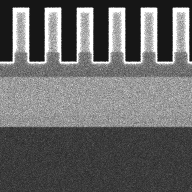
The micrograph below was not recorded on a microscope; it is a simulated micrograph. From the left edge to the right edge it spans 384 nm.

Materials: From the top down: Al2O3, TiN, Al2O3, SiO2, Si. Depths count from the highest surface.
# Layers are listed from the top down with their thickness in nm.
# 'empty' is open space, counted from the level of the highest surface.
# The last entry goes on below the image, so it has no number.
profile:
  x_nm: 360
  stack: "Al2O3 88, TiN 50, Al2O3 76, SiO2 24, Si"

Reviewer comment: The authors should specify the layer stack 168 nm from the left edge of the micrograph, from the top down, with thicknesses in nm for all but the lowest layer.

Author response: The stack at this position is Al2O3 88, TiN 50, Al2O3 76, SiO2 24, Si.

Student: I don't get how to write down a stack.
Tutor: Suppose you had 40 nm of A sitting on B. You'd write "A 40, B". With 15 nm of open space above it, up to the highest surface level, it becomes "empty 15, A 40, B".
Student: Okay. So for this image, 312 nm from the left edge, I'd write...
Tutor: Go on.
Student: Al2O3 88, TiN 50, Al2O3 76, SiO2 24, Si